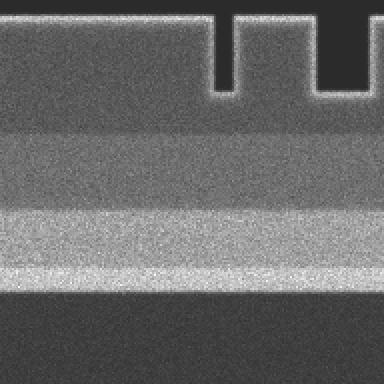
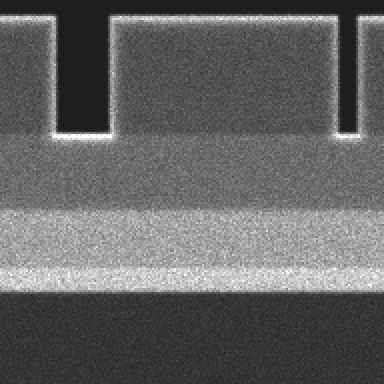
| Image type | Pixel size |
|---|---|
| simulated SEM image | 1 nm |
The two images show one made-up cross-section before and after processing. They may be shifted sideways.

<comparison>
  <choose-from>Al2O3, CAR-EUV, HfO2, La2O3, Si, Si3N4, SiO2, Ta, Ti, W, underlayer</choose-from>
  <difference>underlayer removed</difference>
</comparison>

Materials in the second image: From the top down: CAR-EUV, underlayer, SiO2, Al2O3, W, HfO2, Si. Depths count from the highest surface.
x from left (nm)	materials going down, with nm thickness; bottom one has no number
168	CAR-EUV 76, underlayer 42, SiO2 64, Al2O3 12, W 58, HfO2 24, Si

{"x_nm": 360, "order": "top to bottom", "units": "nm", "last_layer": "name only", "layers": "CAR-EUV 76, underlayer 42, SiO2 64, Al2O3 12, W 58, HfO2 24, Si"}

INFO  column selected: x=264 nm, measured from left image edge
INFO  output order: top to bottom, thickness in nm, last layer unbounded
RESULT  CAR-EUV 76, underlayer 42, SiO2 64, Al2O3 12, W 58, HfO2 24, Si